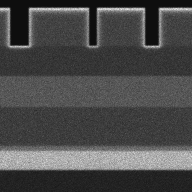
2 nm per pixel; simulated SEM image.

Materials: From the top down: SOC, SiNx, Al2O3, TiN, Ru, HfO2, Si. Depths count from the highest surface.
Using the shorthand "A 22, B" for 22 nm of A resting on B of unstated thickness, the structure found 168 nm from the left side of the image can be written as SOC 76, SiNx 60, Al2O3 62, TiN 78, Ru 10, HfO2 38, Si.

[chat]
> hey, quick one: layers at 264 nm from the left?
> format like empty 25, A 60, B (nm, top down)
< SOC 76, SiNx 60, Al2O3 62, TiN 78, Ru 10, HfO2 38, Si